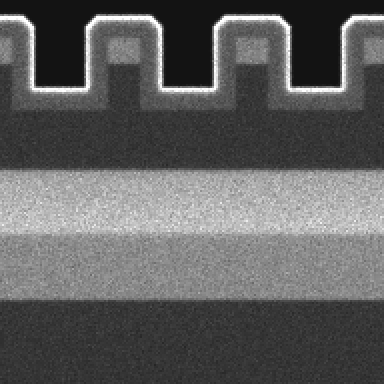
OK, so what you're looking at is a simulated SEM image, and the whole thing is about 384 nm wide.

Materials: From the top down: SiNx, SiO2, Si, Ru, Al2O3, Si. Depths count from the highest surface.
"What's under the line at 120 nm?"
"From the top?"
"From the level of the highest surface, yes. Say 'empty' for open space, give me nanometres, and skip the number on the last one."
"SiNx 22, SiO2 26, Si 106, Ru 64, Al2O3 66, Si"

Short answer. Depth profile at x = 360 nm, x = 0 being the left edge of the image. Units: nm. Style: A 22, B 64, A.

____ SiNx 94, Si 60, Ru 64, Al2O3 66, Si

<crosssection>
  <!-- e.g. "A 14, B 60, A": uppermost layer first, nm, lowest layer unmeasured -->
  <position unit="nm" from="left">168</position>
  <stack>empty 72, SiNx 22, Si 60, Ru 64, Al2O3 66, Si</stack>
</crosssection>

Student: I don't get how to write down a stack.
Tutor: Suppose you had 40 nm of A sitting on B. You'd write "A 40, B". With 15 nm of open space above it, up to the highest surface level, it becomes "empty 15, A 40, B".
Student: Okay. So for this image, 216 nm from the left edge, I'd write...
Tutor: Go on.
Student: empty 8, SiNx 86, Si 60, Ru 64, Al2O3 66, Si